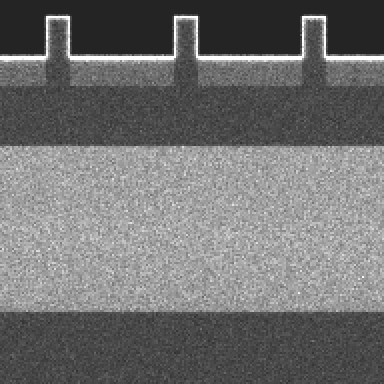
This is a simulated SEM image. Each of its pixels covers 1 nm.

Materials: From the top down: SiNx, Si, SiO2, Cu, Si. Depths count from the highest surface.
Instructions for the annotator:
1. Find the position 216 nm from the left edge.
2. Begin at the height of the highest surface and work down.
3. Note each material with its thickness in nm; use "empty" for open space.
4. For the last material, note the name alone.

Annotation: empty 40, SiNx 30, Si 60, SiO2 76, Cu 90, Si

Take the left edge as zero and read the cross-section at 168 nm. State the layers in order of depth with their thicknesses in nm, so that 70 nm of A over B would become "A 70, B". empty 40, SiNx 30, Si 60, SiO2 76, Cu 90, Si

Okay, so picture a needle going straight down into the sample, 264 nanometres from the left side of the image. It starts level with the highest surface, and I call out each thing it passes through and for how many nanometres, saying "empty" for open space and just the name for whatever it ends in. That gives empty 40, SiNx 30, Si 60, SiO2 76, Cu 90, Si